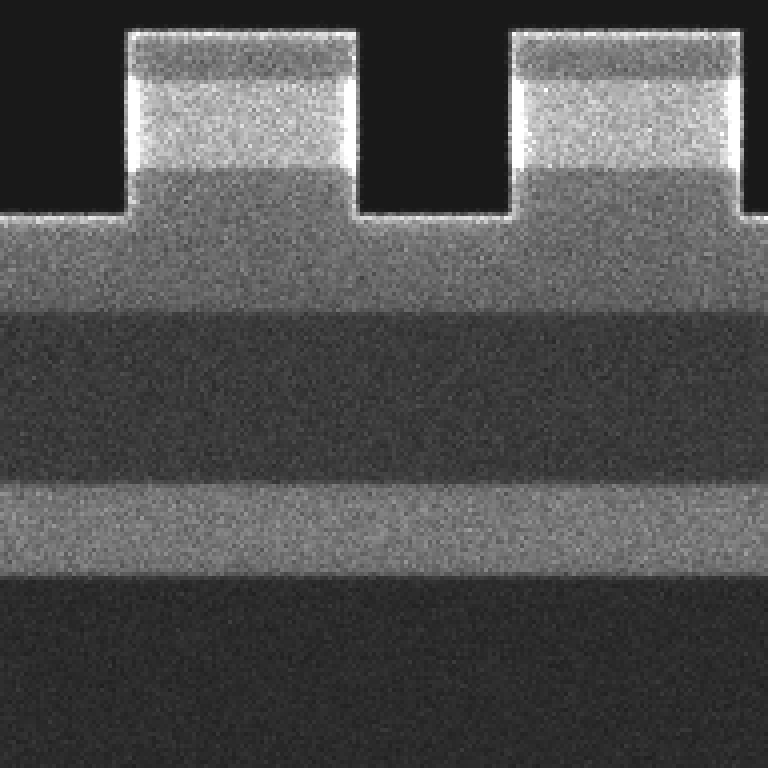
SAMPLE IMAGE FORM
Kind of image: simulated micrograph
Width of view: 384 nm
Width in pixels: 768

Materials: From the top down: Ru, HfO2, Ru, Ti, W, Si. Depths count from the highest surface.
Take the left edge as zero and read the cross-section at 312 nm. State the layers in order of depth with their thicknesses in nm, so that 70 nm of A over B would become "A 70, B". Ru 24, HfO2 44, Ru 72, Ti 86, W 46, Si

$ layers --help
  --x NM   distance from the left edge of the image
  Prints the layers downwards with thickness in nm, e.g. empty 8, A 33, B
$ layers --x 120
Ru 24, HfO2 44, Ru 72, Ti 86, W 46, Si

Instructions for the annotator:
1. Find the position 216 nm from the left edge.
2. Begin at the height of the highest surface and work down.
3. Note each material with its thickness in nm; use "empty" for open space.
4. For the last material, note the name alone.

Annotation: empty 92, Ru 48, Ti 86, W 46, Si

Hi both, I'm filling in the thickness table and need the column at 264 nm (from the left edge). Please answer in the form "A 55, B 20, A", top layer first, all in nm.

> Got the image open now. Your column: Ru 24, HfO2 44, Ru 72, Ti 86, W 46, Si